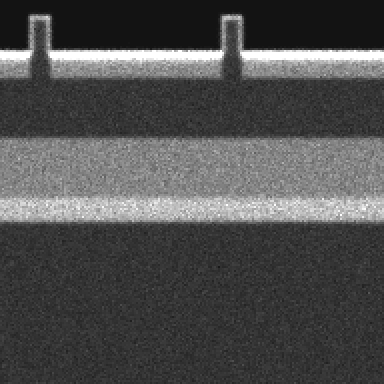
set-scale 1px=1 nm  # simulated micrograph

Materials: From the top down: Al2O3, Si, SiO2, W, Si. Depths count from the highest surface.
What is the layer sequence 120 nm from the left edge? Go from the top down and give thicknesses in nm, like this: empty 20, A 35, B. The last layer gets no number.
empty 36, Al2O3 26, Si 60, SiO2 60, W 24, Si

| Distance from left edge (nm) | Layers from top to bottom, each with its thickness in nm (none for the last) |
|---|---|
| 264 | empty 36, Al2O3 26, Si 60, SiO2 60, W 24, Si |